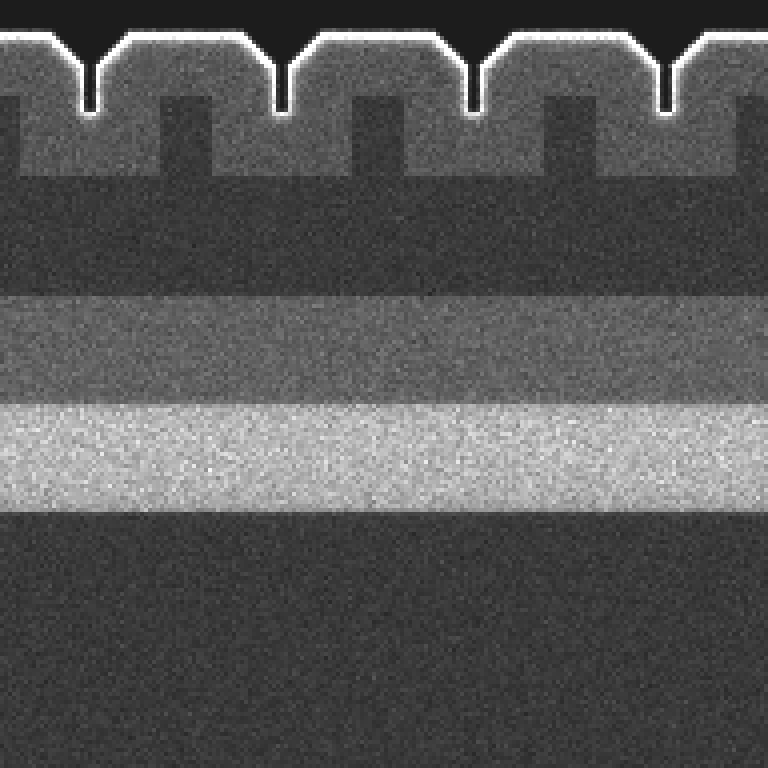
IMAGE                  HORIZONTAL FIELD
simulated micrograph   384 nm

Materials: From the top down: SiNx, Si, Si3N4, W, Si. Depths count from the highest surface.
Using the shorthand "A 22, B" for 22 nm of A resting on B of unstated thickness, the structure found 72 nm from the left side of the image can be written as SiNx 72, Si 60, Si3N4 54, W 54, Si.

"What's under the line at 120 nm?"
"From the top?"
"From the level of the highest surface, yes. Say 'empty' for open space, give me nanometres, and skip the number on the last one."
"SiNx 72, Si 60, Si3N4 54, W 54, Si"